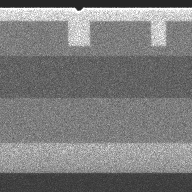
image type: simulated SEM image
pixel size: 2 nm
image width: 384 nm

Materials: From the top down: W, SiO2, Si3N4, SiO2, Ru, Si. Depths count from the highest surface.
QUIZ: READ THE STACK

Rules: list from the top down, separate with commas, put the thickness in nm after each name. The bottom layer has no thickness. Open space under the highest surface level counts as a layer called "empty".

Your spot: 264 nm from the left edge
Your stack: W 26, SiO2 70, Si3N4 84, SiO2 90, Ru 60, Si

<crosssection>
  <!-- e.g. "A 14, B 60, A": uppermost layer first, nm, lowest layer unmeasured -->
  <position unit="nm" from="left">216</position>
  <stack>W 26, SiO2 70, Si3N4 84, SiO2 90, Ru 60, Si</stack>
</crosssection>